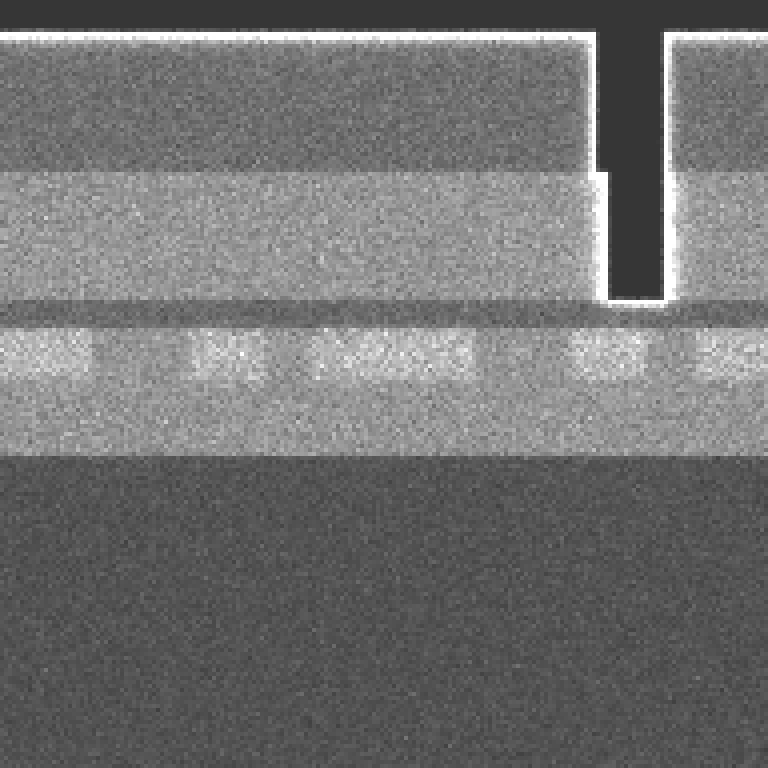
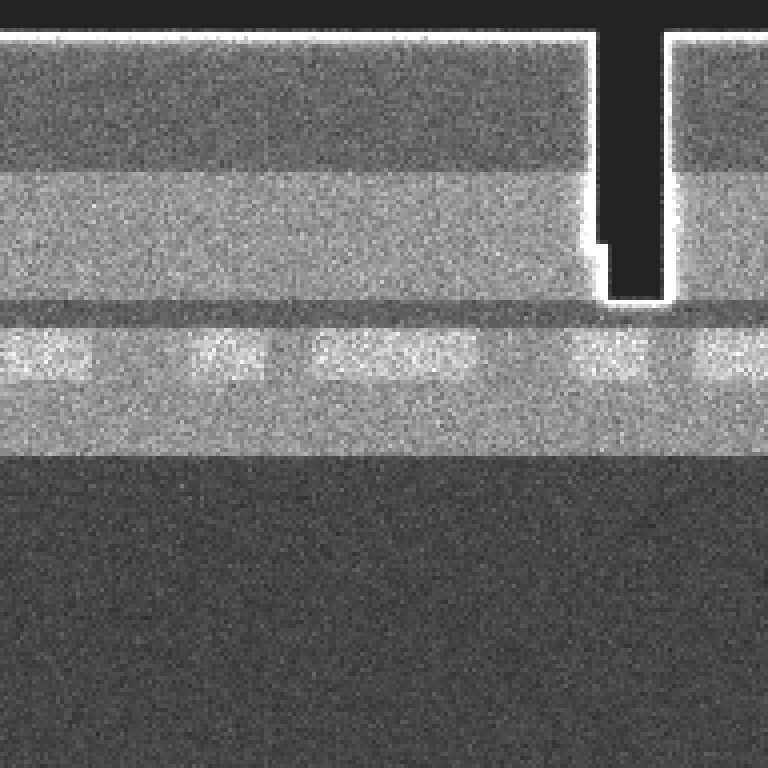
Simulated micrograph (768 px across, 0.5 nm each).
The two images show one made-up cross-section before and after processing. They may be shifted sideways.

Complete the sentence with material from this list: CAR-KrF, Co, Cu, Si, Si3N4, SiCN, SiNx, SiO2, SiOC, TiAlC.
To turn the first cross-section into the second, SiO2 must be removed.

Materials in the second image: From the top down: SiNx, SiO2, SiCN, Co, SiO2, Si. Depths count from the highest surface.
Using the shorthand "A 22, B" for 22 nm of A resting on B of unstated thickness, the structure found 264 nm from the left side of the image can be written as SiNx 70, SiO2 64, SiCN 14, SiO2 64, Si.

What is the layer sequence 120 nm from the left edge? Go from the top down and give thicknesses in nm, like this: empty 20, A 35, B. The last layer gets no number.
SiNx 70, SiO2 64, SiCN 14, Co 26, SiO2 38, Si